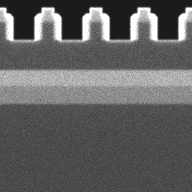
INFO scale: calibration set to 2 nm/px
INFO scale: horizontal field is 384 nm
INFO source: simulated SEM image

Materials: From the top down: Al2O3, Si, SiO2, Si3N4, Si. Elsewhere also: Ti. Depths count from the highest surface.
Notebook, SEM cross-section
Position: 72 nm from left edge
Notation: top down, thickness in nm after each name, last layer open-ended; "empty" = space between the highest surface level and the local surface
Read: empty 16, Al2O3 48, Si 60, SiO2 32, Si3N4 36, Si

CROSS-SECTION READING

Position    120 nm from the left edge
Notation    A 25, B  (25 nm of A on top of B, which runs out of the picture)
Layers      empty 18, Al2O3 46, Si 60, SiO2 32, Si3N4 36, Si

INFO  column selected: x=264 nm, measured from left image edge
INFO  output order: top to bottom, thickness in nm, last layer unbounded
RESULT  empty 16, Al2O3 48, Si 60, SiO2 32, Si3N4 36, Si